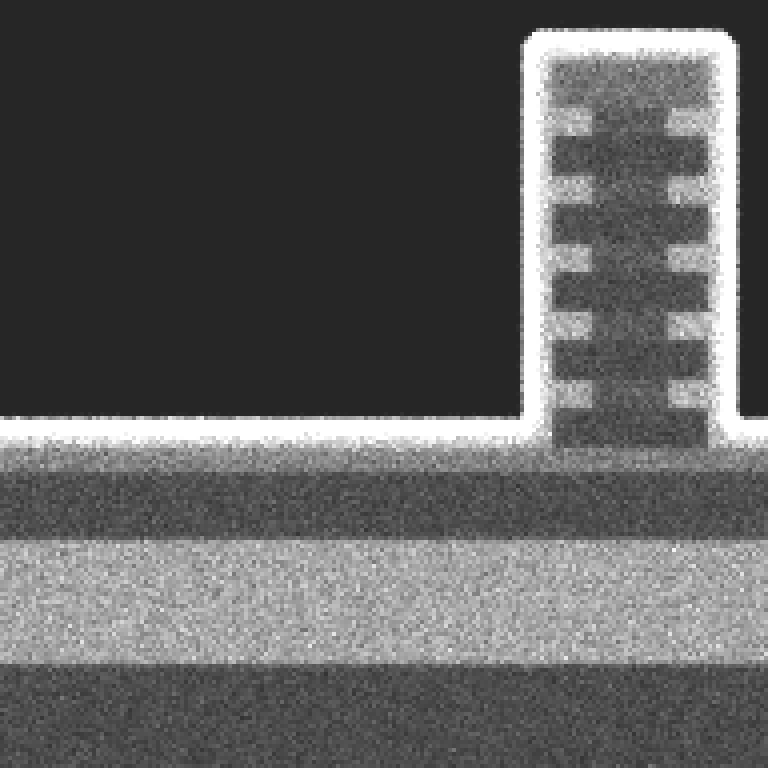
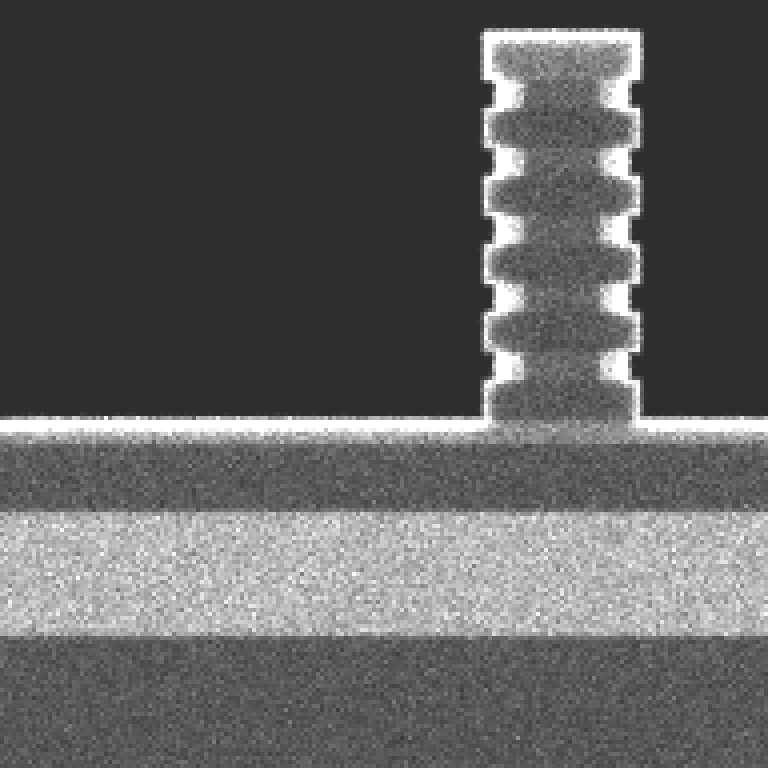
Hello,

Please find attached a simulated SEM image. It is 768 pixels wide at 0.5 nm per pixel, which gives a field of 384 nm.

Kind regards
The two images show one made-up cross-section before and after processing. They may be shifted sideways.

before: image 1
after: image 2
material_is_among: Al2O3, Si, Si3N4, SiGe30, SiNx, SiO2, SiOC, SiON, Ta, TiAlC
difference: Al2O3, removed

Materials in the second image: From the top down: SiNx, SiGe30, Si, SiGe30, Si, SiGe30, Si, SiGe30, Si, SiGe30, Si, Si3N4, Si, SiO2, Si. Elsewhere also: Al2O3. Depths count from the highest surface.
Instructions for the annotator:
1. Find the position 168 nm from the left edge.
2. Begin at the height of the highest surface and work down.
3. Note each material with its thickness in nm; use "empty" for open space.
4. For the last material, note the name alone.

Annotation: empty 194, Si3N4 12, Si 34, SiO2 62, Si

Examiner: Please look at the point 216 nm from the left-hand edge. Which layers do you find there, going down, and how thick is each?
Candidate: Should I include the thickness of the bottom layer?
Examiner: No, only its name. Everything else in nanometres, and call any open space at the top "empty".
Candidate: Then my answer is empty 194, Si3N4 12, Si 34, SiO2 62, Si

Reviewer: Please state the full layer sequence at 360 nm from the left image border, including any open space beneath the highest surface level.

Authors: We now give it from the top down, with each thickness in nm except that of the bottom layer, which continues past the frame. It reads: empty 194, Si3N4 12, Si 34, SiO2 62, Si